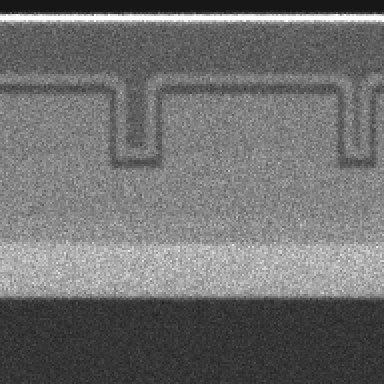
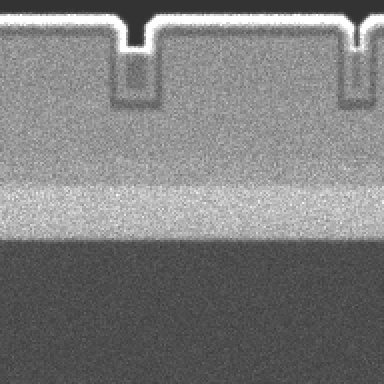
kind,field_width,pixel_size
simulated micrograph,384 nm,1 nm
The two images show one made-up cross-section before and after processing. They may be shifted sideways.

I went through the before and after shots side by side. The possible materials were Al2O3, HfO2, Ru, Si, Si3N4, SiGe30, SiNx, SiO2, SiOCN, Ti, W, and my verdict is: removed, Si3N4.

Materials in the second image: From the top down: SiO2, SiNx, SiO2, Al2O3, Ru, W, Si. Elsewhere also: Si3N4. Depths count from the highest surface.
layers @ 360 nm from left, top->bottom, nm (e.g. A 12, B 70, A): empty 10, SiO2 74, SiNx 10, Al2O3 48, Ru 28, W 54, Si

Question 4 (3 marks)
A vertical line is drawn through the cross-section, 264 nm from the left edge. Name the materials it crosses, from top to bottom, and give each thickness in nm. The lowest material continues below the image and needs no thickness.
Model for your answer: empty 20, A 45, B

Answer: SiO2 10, SiNx 10, SiO2 60, Al2O3 62, Ru 28, W 54, Si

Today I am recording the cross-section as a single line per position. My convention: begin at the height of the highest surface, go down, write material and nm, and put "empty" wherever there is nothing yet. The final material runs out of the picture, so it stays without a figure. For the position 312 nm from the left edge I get SiO2 10, SiNx 10, SiO2 60, Al2O3 62, Ru 28, W 54, Si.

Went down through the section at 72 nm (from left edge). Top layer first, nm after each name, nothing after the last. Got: SiO2 10, SiNx 10, SiO2 60, Al2O3 62, Ru 28, W 54, Si